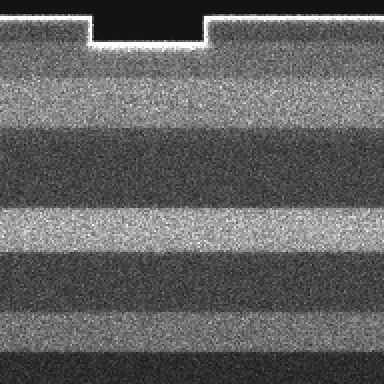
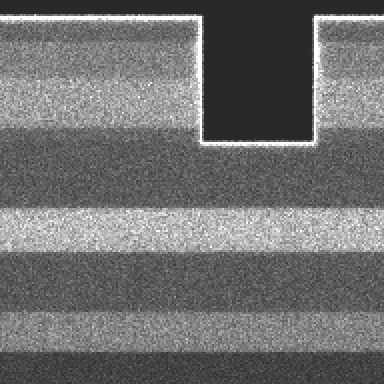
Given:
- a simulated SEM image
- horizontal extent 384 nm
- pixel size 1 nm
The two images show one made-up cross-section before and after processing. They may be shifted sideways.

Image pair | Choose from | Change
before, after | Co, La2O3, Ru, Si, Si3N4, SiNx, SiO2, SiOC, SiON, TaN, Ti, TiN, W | Ru and SiO2 and TiN (removed)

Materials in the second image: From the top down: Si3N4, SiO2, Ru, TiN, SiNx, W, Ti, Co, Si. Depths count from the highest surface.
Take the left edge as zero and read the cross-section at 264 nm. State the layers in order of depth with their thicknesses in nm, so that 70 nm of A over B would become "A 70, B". empty 126, SiNx 66, W 44, Ti 60, Co 40, Si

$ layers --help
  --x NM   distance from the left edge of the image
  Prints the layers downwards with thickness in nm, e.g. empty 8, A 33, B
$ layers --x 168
Si3N4 26, SiO2 36, Ru 50, TiN 14, SiNx 66, W 44, Ti 60, Co 40, Si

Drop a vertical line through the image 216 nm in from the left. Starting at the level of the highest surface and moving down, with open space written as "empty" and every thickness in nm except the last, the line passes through empty 126, SiNx 66, W 44, Ti 60, Co 40, Si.